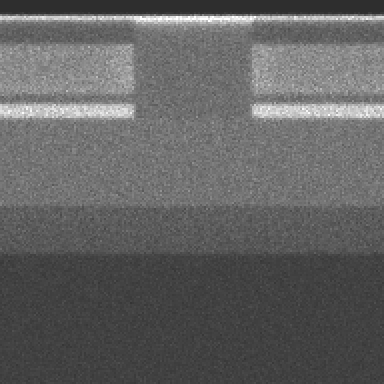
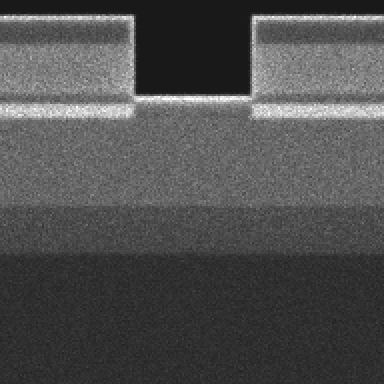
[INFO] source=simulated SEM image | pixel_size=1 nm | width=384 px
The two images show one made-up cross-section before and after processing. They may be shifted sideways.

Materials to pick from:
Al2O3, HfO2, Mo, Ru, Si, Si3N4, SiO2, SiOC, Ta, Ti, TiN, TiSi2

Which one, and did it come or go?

SiO2 - removed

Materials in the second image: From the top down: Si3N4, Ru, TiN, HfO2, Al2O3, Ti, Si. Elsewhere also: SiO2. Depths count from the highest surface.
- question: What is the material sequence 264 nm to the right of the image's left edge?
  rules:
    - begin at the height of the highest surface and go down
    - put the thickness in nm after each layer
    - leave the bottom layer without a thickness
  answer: Si3N4 28, Ru 50, TiN 10, HfO2 14, Al2O3 88, Ti 48, Si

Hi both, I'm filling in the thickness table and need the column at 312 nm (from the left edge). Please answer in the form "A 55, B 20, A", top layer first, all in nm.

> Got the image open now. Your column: Si3N4 28, Ru 50, TiN 10, HfO2 14, Al2O3 88, Ti 48, Si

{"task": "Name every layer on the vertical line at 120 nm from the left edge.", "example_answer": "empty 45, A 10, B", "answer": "Si3N4 28, Ru 50, TiN 10, HfO2 14, Al2O3 88, Ti 48, Si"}